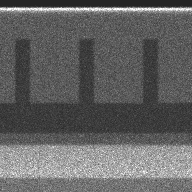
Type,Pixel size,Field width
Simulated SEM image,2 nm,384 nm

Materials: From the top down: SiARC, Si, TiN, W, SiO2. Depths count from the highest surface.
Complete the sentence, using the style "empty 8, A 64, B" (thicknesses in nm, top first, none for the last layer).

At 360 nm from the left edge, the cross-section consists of SiARC 190, Si 60, TiN 24, W 66, SiO2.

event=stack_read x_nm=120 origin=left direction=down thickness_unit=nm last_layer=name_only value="SiARC 190, Si 60, TiN 24, W 66, SiO2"